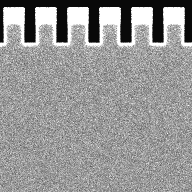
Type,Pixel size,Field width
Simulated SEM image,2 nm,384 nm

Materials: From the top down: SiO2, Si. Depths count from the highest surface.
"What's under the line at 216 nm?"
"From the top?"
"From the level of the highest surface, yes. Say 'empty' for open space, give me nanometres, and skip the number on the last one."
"SiO2 32, Si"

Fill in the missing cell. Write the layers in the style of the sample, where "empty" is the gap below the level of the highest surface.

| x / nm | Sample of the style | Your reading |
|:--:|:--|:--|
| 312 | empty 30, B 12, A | empty 70, Si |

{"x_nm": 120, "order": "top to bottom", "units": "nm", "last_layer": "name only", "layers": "empty 70, Si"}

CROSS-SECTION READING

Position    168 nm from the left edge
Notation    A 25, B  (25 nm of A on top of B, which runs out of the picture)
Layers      SiO2 32, Si